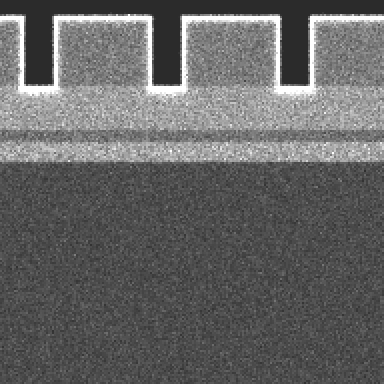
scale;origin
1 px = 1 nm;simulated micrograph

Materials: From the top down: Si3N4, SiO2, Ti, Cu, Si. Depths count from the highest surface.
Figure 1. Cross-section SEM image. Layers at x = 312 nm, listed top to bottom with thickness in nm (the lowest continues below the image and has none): Si3N4 70, SiO2 44, Ti 12, Cu 20, Si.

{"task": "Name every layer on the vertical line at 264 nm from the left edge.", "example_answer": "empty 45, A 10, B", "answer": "Si3N4 70, SiO2 44, Ti 12, Cu 20, Si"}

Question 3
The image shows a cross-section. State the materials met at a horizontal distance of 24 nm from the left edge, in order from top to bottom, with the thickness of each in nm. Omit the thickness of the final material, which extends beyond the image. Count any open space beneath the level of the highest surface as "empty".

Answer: empty 70, SiO2 44, Ti 12, Cu 20, Si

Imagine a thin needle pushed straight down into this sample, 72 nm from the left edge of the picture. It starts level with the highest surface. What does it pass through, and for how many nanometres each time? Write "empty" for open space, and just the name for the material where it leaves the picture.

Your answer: Si3N4 70, SiO2 44, Ti 12, Cu 20, Si